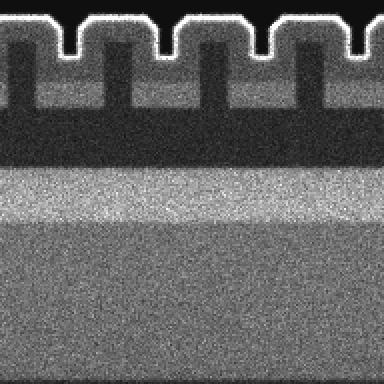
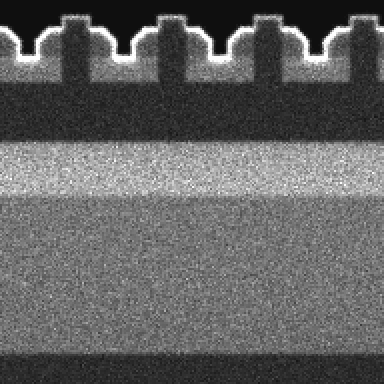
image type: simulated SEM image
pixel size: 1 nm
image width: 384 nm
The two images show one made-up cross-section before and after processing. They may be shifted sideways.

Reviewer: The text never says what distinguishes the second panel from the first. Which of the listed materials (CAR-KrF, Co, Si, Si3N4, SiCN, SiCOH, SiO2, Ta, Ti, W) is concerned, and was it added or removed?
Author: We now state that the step removed Si3N4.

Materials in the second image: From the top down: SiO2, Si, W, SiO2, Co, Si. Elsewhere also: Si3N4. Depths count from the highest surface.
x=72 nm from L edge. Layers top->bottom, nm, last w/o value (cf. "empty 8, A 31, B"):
Si 126, W 54, SiO2 78, Co 80, Si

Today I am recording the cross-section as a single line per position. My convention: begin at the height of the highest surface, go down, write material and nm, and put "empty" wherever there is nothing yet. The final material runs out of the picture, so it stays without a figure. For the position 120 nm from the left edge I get empty 40, SiO2 26, Si 60, W 54, SiO2 78, Co 80, Si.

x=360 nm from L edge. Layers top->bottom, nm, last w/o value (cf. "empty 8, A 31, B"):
Si 126, W 54, SiO2 78, Co 80, Si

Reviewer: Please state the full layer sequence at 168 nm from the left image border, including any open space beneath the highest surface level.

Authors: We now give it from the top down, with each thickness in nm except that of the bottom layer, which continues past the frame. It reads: Si 126, W 54, SiO2 78, Co 80, Si